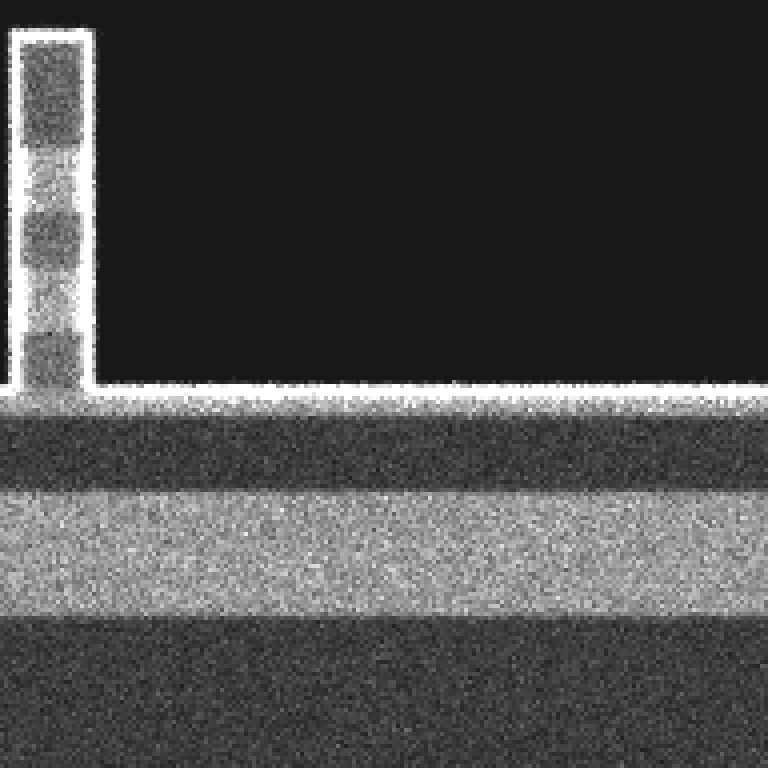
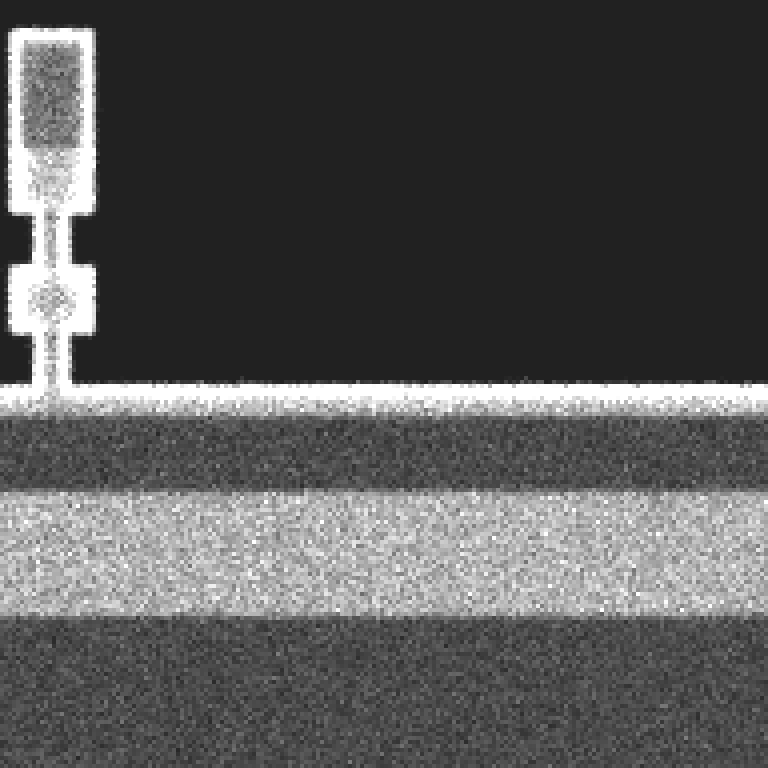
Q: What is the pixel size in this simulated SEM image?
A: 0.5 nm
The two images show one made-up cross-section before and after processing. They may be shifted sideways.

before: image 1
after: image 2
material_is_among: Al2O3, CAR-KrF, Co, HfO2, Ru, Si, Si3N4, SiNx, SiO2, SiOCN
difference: Si3N4, removed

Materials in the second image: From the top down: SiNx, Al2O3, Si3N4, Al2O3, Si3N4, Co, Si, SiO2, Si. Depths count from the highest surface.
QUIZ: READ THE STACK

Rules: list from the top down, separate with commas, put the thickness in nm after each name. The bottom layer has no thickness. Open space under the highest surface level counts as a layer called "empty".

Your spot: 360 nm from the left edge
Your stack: empty 178, Co 14, Si 38, SiO2 62, Si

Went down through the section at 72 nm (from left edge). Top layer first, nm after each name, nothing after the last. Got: empty 178, Co 14, Si 38, SiO2 62, Si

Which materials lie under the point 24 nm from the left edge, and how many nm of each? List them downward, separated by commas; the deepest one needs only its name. SiNx 58, Al2O3 32, Si3N4 28, Al2O3 32, Si3N4 28, Co 14, Si 38, SiO2 62, Si